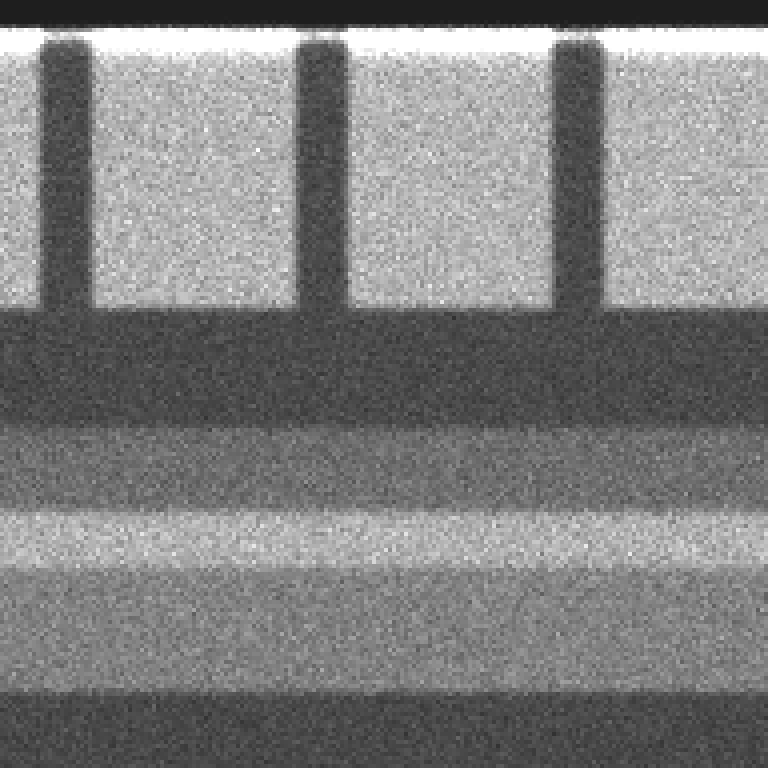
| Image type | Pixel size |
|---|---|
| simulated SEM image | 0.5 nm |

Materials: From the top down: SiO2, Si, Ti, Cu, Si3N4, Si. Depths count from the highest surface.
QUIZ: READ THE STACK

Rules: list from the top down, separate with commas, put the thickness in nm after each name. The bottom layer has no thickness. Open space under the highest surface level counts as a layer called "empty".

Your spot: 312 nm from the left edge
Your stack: SiO2 138, Si 60, Ti 42, Cu 28, Si3N4 62, Si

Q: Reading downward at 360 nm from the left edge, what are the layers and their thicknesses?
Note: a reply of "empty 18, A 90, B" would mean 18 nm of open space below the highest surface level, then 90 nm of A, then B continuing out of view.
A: SiO2 138, Si 60, Ti 42, Cu 28, Si3N4 62, Si